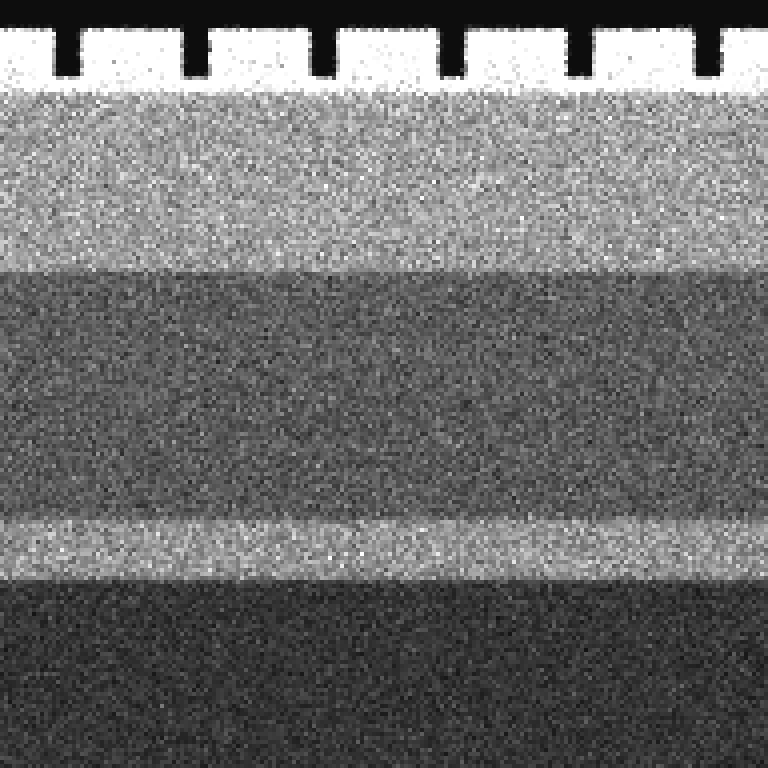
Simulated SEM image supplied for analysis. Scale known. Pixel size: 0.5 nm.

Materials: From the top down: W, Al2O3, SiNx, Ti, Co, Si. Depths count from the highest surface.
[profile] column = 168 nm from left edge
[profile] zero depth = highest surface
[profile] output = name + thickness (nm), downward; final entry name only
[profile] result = empty 24, W 6, Al2O3 90, SiNx 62, Ti 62, Co 30, Si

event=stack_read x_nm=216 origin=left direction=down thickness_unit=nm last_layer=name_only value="W 30, Al2O3 90, SiNx 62, Ti 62, Co 30, Si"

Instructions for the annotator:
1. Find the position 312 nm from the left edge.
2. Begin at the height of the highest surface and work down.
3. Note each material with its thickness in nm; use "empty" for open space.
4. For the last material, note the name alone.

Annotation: W 30, Al2O3 90, SiNx 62, Ti 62, Co 30, Si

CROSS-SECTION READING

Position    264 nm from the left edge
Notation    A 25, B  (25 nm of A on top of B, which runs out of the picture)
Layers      W 30, Al2O3 90, SiNx 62, Ti 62, Co 30, Si